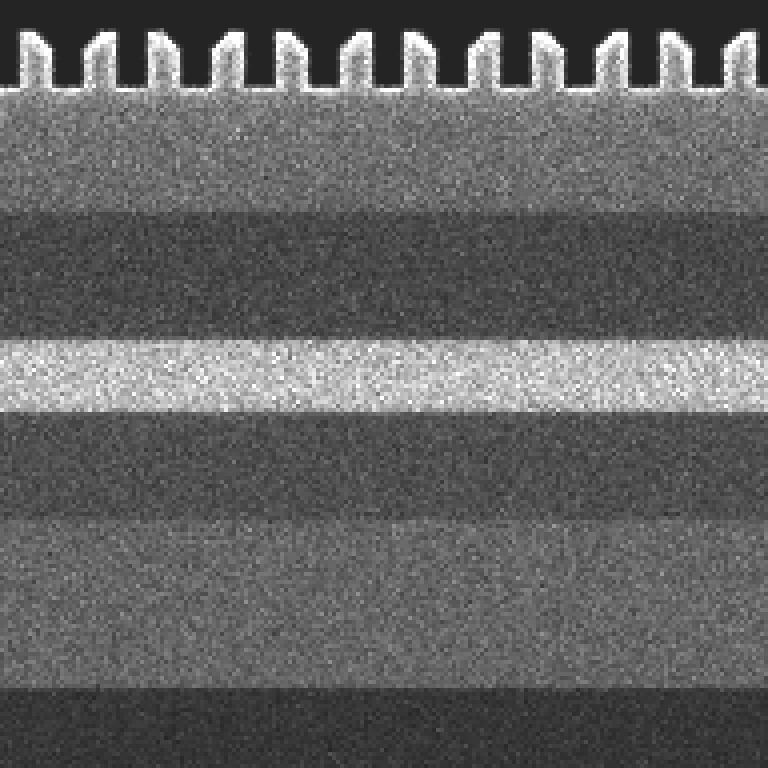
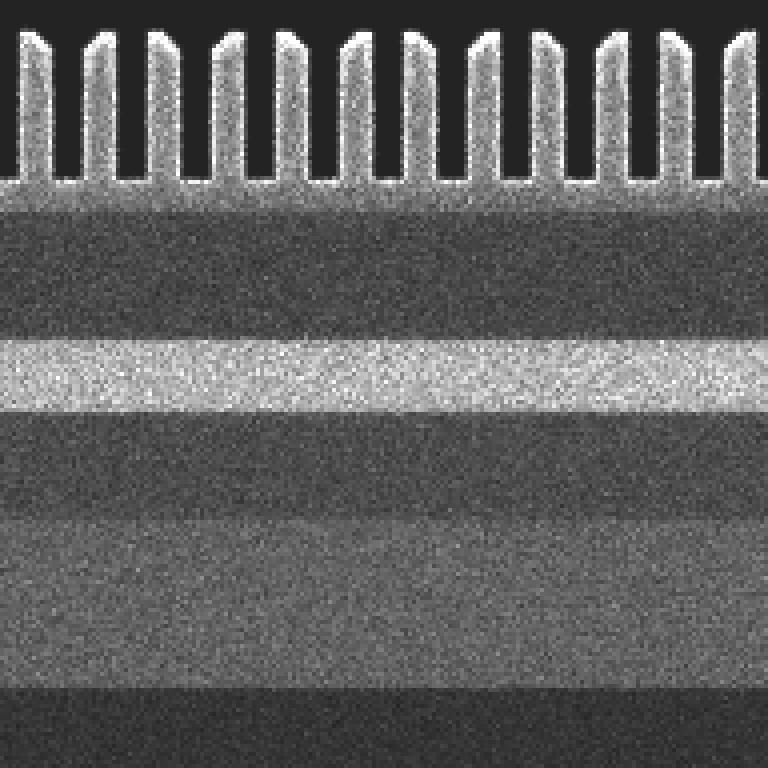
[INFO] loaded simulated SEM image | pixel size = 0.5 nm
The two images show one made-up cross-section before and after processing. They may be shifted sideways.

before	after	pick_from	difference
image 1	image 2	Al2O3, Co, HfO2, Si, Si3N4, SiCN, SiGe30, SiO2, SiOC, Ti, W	Co removed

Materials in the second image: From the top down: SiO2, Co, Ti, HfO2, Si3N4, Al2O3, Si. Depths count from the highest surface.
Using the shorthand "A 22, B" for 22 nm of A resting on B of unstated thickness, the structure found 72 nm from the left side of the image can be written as empty 74, Co 16, Ti 64, HfO2 36, Si3N4 54, Al2O3 84, Si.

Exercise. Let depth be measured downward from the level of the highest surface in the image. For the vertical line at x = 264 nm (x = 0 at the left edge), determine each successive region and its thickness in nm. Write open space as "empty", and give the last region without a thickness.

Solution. empty 74, Co 16, Ti 64, HfO2 36, Si3N4 54, Al2O3 84, Si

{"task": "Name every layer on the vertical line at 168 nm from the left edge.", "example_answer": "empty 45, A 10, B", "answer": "empty 74, Co 16, Ti 64, HfO2 36, Si3N4 54, Al2O3 84, Si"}